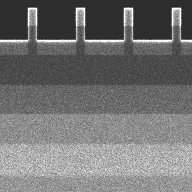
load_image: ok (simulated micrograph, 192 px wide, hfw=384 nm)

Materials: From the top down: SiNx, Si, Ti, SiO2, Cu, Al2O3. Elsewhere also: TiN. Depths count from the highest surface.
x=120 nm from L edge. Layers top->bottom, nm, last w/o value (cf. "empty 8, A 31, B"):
empty 64, SiNx 30, Si 60, Ti 58, SiO2 60, Cu 64, Al2O3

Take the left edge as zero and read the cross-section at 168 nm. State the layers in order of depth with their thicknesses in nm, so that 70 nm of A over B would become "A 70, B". TiN 36, Si 118, Ti 58, SiO2 60, Cu 64, Al2O3